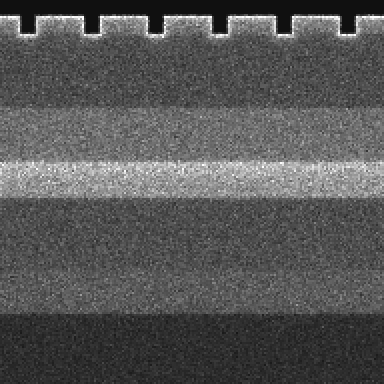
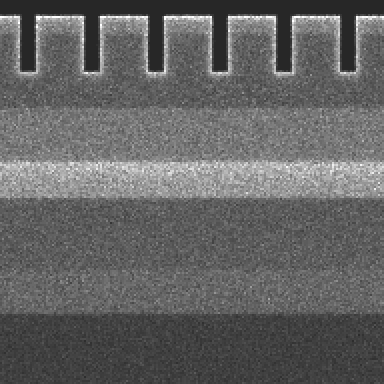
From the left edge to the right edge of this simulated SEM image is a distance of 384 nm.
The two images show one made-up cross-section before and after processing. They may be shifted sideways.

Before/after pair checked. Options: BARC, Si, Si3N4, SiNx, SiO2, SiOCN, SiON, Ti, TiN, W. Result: removed SiNx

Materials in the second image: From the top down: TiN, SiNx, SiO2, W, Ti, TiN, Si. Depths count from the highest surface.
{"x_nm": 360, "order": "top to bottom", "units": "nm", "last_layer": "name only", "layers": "TiN 18, SiNx 74, SiO2 54, W 36, Ti 72, TiN 44, Si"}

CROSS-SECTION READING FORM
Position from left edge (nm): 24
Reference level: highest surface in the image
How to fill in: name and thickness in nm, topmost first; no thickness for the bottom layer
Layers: empty 56, SiNx 36, SiO2 54, W 36, Ti 72, TiN 44, Si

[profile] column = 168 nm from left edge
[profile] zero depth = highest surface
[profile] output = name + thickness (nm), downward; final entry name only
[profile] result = TiN 18, SiNx 74, SiO2 54, W 36, Ti 72, TiN 44, Si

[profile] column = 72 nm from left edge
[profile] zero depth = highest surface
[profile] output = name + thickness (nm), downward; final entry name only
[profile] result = TiN 18, SiNx 74, SiO2 54, W 36, Ti 72, TiN 44, Si